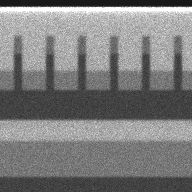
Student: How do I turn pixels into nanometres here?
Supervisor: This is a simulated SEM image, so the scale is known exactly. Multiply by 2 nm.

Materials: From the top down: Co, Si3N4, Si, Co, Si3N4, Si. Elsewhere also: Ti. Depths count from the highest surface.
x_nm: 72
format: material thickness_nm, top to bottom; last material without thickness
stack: Co 126, Si3N4 38, Si 60, Co 42, Si3N4 72, Si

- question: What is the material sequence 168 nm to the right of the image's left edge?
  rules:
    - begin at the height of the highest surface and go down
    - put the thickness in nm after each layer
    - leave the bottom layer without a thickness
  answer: Co 56, Ti 36, Si 132, Co 42, Si3N4 72, Si